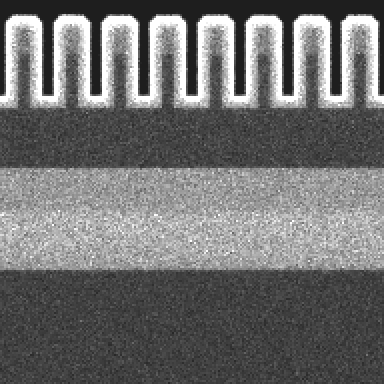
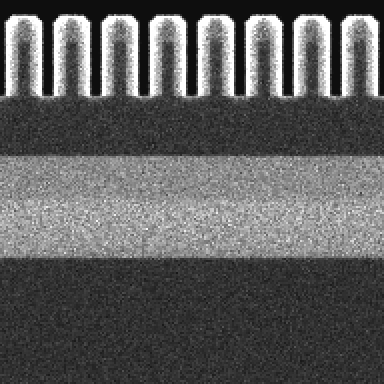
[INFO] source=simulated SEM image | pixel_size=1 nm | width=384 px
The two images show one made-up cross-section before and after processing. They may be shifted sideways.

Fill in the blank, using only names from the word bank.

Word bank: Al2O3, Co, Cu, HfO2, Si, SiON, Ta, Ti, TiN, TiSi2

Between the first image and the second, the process removed Al2O3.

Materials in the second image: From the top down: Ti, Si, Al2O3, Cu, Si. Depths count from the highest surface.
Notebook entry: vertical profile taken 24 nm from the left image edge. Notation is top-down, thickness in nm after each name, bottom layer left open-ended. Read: Ti 26, Si 114, Al2O3 44, Cu 58, Si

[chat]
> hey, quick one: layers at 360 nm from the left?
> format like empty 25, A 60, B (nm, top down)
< Ti 26, Si 114, Al2O3 44, Cu 58, Si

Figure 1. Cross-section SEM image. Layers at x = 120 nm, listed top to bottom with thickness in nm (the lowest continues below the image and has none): Ti 26, Si 114, Al2O3 44, Cu 58, Si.